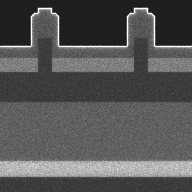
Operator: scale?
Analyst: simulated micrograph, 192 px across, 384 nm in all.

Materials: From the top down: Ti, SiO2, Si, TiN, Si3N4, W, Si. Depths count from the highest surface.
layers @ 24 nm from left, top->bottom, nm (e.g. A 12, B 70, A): empty 76, Ti 24, SiO2 28, Si 60, TiN 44, Si3N4 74, W 32, Si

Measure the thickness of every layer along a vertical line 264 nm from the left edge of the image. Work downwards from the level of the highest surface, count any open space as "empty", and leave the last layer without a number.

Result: empty 10, Ti 90, SiO2 28, Si 60, TiN 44, Si3N4 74, W 32, Si